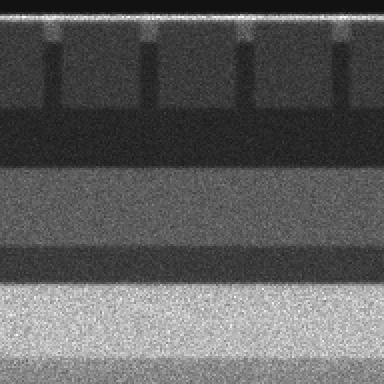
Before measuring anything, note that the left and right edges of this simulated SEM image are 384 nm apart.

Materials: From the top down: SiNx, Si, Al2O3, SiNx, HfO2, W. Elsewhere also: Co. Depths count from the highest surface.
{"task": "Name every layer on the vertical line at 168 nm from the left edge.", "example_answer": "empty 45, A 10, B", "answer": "SiNx 92, Si 60, Al2O3 78, SiNx 38, HfO2 74, W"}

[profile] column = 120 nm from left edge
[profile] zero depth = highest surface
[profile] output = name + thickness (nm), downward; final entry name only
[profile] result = SiNx 92, Si 60, Al2O3 78, SiNx 38, HfO2 74, W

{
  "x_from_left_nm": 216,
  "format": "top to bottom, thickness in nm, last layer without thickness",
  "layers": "SiNx 92, Si 60, Al2O3 78, SiNx 38, HfO2 74, W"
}